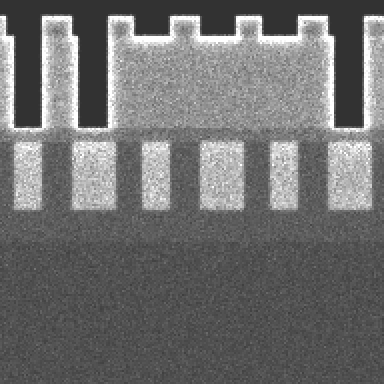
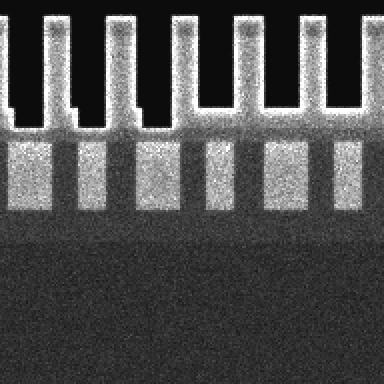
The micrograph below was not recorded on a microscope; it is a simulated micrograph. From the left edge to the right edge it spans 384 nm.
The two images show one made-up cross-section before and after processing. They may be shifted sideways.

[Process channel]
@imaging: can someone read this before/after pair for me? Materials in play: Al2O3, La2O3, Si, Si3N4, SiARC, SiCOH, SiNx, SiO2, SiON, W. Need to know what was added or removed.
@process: SiO2 removed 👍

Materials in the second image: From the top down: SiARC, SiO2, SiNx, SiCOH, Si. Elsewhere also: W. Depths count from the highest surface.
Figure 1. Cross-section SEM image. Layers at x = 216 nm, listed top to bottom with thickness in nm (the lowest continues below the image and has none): empty 92, SiO2 20, SiNx 14, W 68, SiCOH 32, Si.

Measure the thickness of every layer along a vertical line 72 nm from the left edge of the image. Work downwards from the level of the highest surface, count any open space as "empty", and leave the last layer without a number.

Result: empty 92, SiO2 20, SiNx 14, SiCOH 100, Si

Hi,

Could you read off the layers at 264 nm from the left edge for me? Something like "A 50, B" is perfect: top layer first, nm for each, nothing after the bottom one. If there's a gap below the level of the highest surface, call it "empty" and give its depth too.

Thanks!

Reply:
empty 92, SiO2 20, SiNx 14, W 68, SiCOH 32, Si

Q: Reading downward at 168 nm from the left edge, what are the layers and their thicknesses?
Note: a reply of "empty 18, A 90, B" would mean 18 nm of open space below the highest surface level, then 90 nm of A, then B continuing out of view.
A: empty 112, SiNx 14, W 68, SiCOH 32, Si